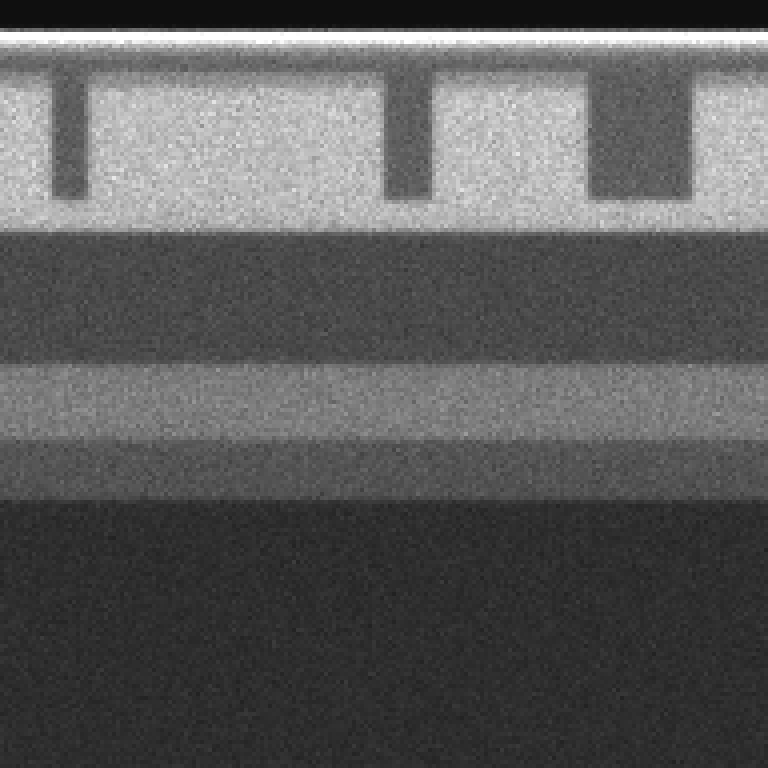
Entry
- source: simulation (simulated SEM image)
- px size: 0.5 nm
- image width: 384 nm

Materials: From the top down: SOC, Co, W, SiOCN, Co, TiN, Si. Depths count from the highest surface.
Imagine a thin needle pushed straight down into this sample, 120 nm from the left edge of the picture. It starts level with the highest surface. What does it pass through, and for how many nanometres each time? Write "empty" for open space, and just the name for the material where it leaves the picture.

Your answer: SOC 20, Co 8, W 72, SiOCN 66, Co 38, TiN 30, Si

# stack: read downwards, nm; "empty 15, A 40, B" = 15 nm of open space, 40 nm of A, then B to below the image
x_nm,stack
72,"SOC 20, Co 8, W 72, SiOCN 66, Co 38, TiN 30, Si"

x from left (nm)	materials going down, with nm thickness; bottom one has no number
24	SOC 20, Co 8, W 72, SiOCN 66, Co 38, TiN 30, Si